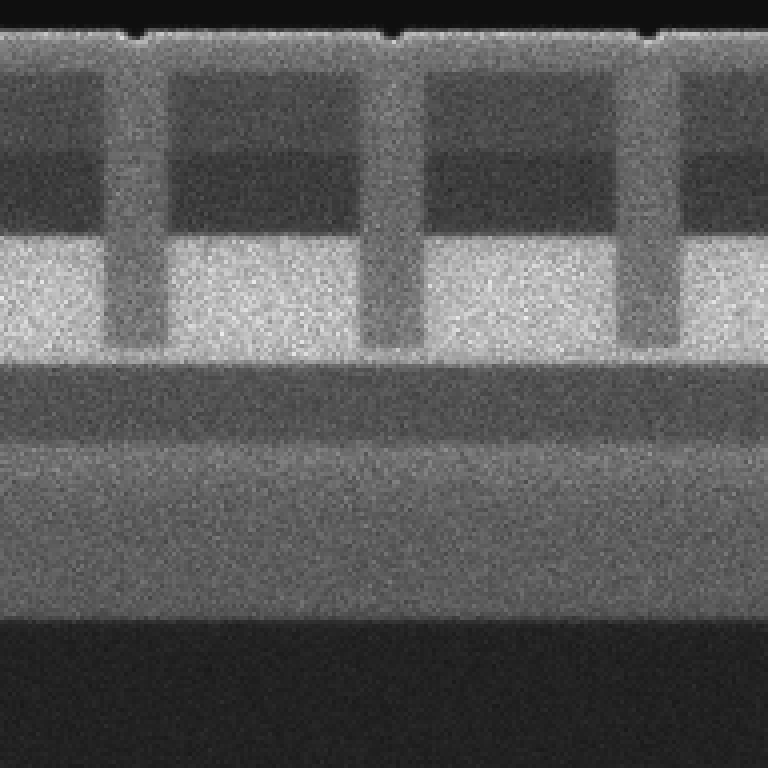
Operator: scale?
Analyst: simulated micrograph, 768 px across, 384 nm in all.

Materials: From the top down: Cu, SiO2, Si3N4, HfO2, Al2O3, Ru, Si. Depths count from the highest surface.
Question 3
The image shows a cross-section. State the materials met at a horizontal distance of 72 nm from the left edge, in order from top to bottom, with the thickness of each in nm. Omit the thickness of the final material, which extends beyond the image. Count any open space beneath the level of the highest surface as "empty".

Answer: empty 2, Cu 156, HfO2 8, Al2O3 40, Ru 88, Si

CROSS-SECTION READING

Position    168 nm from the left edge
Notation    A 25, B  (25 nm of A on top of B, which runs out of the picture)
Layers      Cu 20, SiO2 40, Si3N4 42, HfO2 64, Al2O3 40, Ru 88, Si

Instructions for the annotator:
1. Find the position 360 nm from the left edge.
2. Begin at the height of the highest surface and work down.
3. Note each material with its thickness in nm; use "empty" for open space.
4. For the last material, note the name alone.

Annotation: Cu 20, SiO2 40, Si3N4 42, HfO2 64, Al2O3 40, Ru 88, Si